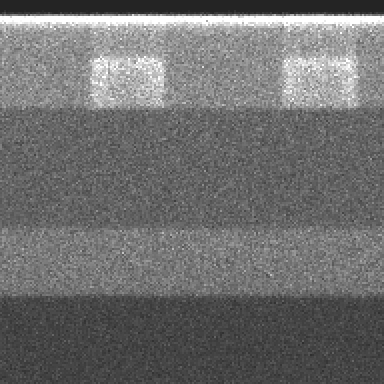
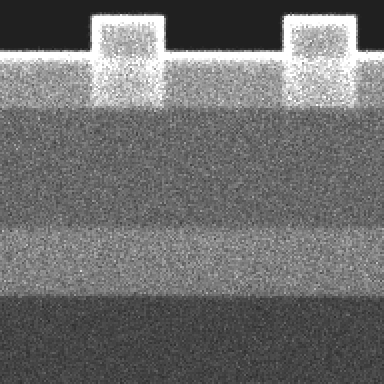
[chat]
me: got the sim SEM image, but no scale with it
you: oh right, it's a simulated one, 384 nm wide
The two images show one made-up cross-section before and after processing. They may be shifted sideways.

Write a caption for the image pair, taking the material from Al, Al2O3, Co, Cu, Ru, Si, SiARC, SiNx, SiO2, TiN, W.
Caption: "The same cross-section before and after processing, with SiO2 removed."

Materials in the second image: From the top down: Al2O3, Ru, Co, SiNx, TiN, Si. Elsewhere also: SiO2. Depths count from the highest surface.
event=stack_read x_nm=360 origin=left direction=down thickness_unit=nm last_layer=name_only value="empty 36, SiO2 56, SiNx 120, TiN 68, Si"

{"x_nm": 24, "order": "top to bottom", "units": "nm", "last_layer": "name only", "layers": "empty 36, SiO2 56, SiNx 120, TiN 68, Si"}